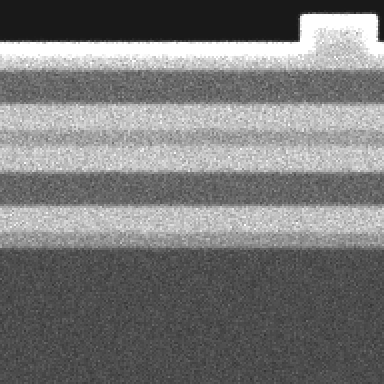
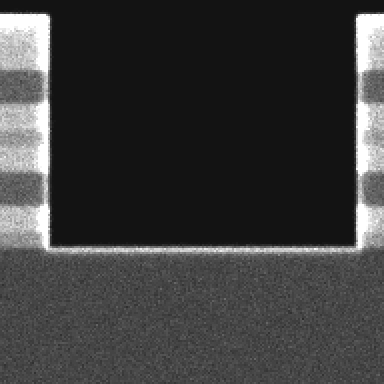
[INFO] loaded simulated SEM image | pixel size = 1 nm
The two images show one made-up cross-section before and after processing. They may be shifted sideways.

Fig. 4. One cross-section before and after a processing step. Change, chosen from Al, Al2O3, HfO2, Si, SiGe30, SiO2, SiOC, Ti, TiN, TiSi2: SiGe30 and SiO2 and TiN removed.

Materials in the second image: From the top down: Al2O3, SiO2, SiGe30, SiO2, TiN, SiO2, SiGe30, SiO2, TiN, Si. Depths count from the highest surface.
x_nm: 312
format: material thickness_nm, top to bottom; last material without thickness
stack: empty 232, Si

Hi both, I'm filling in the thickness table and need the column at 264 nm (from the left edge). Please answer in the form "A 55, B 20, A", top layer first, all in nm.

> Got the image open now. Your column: empty 232, Si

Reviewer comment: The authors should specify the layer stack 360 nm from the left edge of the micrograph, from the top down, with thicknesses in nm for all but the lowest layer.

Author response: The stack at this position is Al2O3 28, SiO2 26, SiGe30 34, SiO2 26, TiN 16, SiO2 26, SiGe30 34, SiO2 26, TiN 16, Si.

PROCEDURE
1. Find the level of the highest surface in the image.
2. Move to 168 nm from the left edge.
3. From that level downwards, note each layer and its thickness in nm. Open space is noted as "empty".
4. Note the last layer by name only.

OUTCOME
empty 232, Si